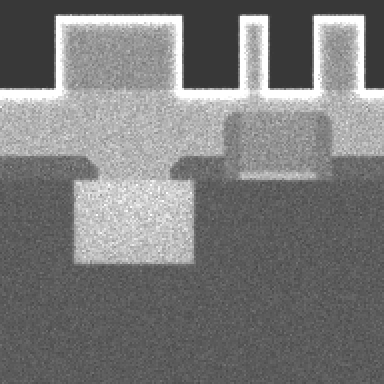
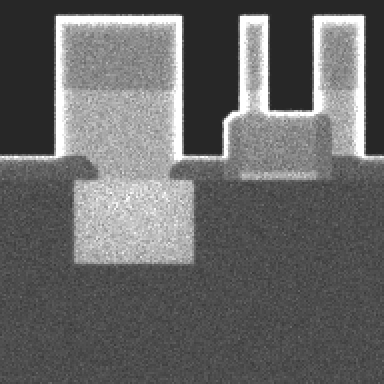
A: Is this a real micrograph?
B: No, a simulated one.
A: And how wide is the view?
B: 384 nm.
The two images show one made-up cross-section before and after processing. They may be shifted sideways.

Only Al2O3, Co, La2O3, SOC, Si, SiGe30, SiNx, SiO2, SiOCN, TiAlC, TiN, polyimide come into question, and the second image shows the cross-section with SiO2 removed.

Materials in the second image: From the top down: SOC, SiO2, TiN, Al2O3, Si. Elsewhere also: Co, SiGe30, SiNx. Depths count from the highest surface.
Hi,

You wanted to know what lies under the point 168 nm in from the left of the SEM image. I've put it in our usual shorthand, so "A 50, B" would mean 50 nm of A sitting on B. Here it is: SOC 74, SiO2 90, Co 84, Si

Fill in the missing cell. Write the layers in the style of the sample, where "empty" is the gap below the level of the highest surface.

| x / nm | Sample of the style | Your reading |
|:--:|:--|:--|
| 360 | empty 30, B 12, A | SOC 74, SiO2 66, SiGe30 24, Si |